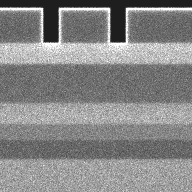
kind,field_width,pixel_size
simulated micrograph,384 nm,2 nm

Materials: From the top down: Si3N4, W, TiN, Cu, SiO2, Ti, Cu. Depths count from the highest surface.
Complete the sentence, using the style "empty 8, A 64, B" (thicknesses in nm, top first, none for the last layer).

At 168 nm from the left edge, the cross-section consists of Si3N4 70, W 42, TiN 78, Cu 42, SiO2 32, Ti 38, Cu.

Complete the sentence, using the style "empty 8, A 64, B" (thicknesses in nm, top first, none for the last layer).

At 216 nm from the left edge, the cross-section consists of Si3N4 70, W 42, TiN 78, Cu 42, SiO2 32, Ti 38, Cu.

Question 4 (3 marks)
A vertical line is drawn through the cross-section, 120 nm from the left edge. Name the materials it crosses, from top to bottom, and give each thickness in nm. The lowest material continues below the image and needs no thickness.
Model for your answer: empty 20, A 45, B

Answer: Si3N4 70, W 42, TiN 78, Cu 42, SiO2 32, Ti 38, Cu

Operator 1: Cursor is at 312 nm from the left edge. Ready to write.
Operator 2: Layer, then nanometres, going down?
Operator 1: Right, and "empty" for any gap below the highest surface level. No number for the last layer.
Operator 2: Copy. Si3N4 70, W 42, TiN 78, Cu 42, SiO2 32, Ti 38, Cu